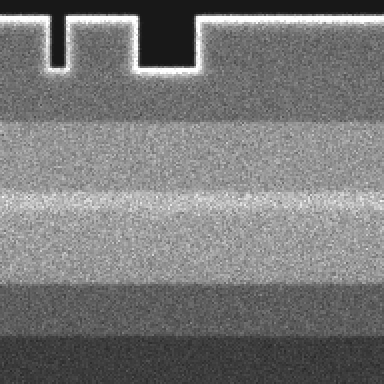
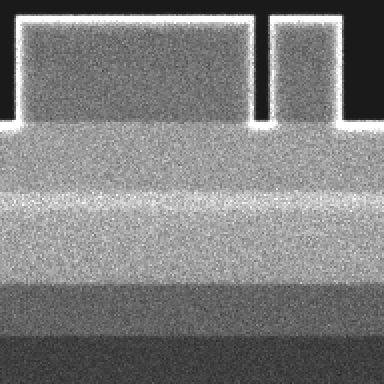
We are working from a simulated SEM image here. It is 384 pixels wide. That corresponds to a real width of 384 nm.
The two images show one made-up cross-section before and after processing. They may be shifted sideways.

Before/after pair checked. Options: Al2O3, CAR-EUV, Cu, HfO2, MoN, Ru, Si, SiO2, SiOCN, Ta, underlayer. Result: removed underlayer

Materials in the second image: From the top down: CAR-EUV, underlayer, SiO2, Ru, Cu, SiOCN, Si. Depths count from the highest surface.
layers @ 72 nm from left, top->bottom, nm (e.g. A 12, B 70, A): CAR-EUV 52, underlayer 54, SiO2 70, Ru 18, Cu 74, SiOCN 52, Si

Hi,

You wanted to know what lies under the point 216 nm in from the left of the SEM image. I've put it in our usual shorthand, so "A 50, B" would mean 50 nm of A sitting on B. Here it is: CAR-EUV 52, underlayer 54, SiO2 70, Ru 18, Cu 74, SiOCN 52, Si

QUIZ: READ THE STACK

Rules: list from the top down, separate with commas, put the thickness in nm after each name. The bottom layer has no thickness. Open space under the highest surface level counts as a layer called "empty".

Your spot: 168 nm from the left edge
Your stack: CAR-EUV 52, underlayer 54, SiO2 70, Ru 18, Cu 74, SiOCN 52, Si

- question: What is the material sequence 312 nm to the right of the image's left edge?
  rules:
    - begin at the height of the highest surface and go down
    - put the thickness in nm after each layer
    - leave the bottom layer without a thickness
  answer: CAR-EUV 52, underlayer 54, SiO2 70, Ru 18, Cu 74, SiOCN 52, Si